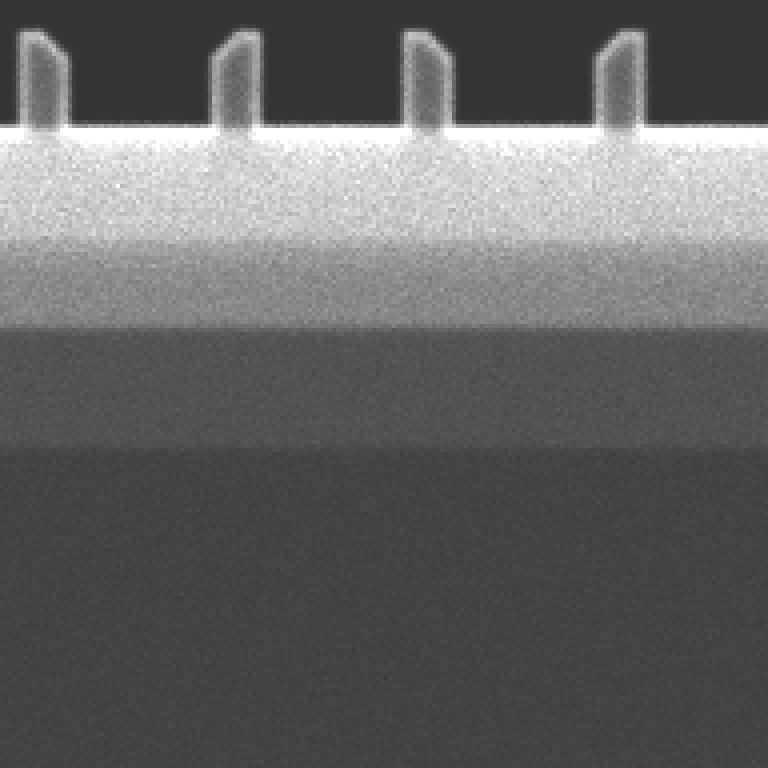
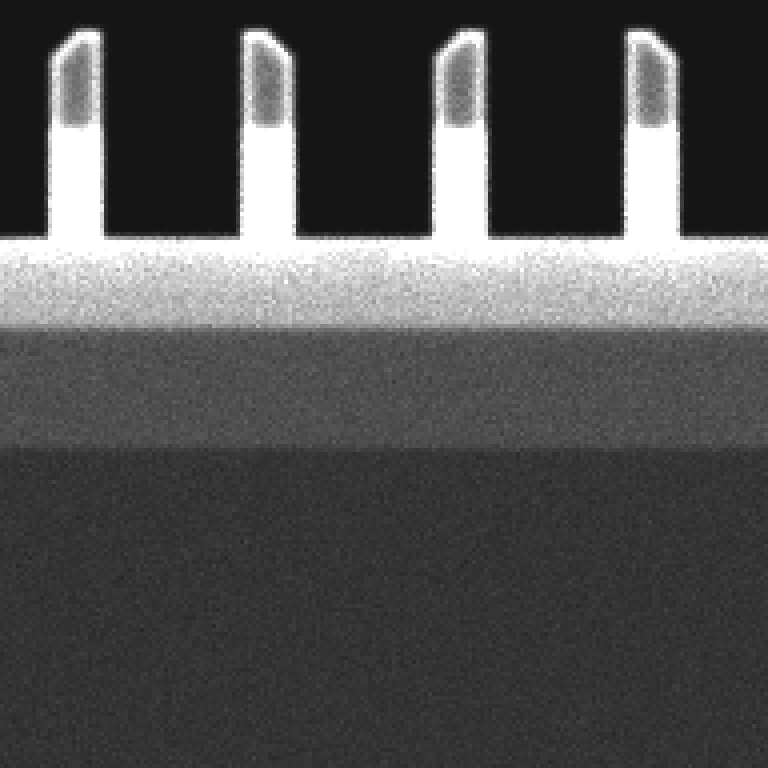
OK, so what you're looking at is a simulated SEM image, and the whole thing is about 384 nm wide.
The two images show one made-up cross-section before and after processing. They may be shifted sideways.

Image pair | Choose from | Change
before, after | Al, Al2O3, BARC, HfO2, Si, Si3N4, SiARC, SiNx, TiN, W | HfO2 (removed)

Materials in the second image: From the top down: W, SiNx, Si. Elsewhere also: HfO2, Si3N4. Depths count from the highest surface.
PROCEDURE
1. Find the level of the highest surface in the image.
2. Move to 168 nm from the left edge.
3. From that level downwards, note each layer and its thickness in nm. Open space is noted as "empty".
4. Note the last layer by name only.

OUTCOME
empty 104, W 44, SiNx 60, Si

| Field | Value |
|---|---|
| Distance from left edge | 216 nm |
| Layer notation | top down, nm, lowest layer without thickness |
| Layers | empty 104, W 44, SiNx 60, Si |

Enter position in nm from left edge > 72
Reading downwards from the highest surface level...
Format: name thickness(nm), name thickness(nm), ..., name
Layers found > empty 104, W 44, SiNx 60, Si